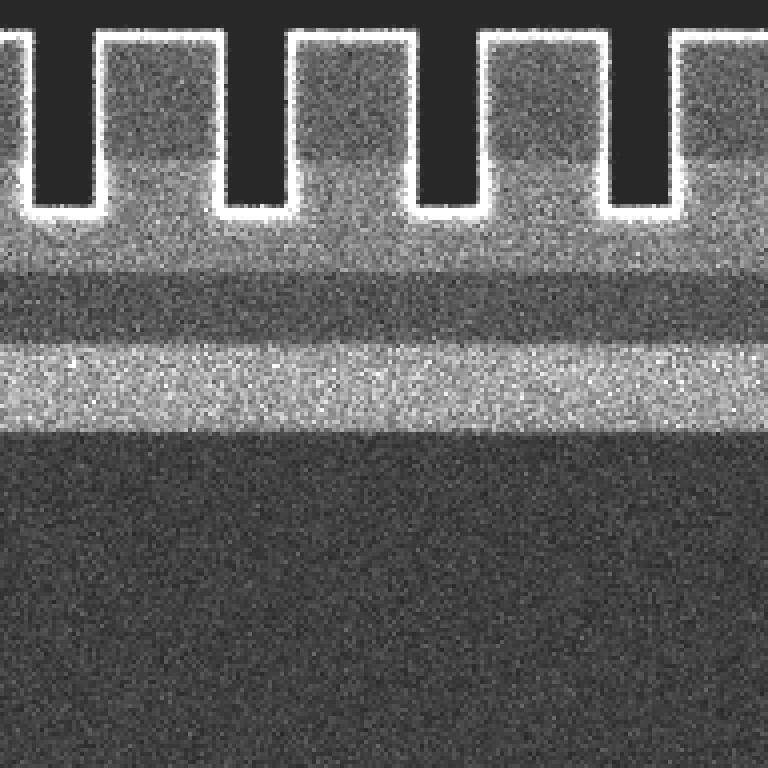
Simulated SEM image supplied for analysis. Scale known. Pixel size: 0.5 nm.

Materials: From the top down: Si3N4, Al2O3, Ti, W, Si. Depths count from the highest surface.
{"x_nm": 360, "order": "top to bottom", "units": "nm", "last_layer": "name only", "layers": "Si3N4 64, Al2O3 56, Ti 36, W 44, Si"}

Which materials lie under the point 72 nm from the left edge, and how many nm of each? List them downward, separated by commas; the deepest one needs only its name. Si3N4 64, Al2O3 56, Ti 36, W 44, Si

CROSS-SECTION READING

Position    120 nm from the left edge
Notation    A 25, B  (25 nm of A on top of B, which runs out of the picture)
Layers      empty 88, Al2O3 32, Ti 36, W 44, Si